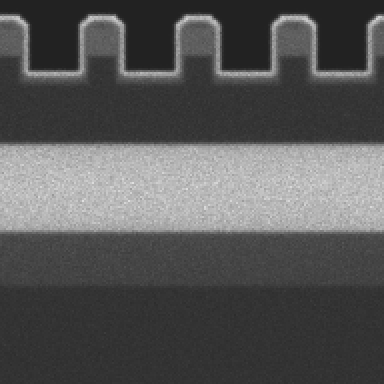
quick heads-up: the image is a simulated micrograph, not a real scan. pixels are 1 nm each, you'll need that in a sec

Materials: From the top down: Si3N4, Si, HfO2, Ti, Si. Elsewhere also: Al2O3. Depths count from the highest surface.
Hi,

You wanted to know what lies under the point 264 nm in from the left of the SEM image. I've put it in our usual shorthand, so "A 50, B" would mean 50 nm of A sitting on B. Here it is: empty 56, Si3N4 12, Si 60, HfO2 88, Ti 54, Si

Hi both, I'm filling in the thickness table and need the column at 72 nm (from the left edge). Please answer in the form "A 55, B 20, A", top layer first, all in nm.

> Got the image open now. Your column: empty 56, Si3N4 12, Si 60, HfO2 88, Ti 54, Si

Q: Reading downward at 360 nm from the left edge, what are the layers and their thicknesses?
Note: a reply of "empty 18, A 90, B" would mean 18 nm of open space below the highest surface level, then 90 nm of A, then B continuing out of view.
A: empty 56, Si3N4 12, Si 60, HfO2 88, Ti 54, Si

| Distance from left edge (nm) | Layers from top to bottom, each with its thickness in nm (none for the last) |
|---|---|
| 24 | empty 6, Si3N4 62, Si 60, HfO2 88, Ti 54, Si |